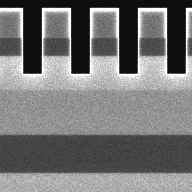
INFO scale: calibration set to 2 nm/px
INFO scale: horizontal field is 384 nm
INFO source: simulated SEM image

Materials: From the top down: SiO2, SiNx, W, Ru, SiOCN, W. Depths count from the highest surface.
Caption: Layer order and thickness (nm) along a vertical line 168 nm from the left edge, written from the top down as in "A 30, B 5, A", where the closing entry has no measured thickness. empty 132, W 32, Ru 90, SiOCN 76, W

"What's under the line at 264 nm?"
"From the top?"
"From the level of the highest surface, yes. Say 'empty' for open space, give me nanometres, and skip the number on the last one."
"empty 132, W 32, Ru 90, SiOCN 76, W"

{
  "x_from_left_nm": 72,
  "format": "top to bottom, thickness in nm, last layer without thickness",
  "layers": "empty 132, W 32, Ru 90, SiOCN 76, W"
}